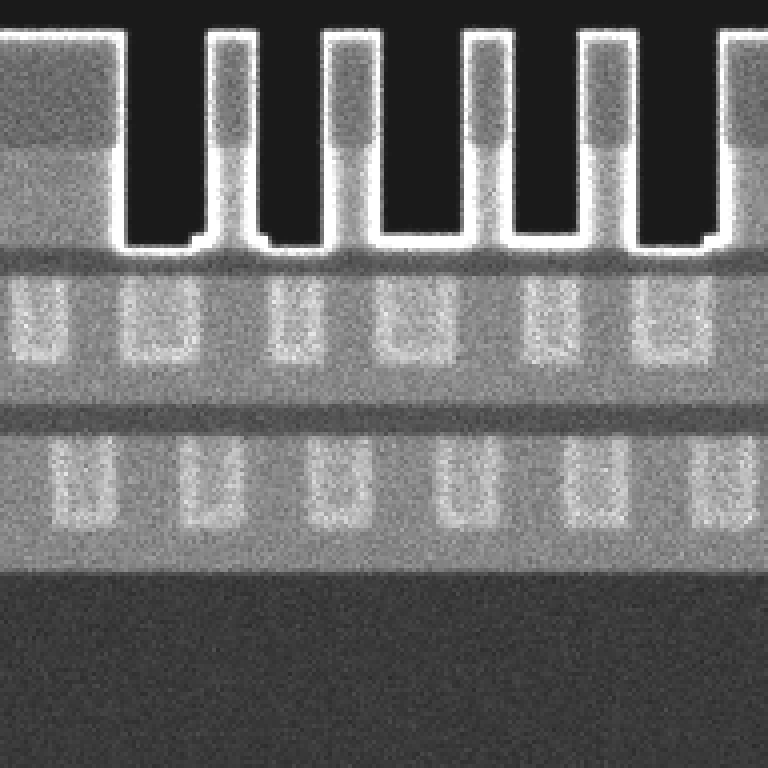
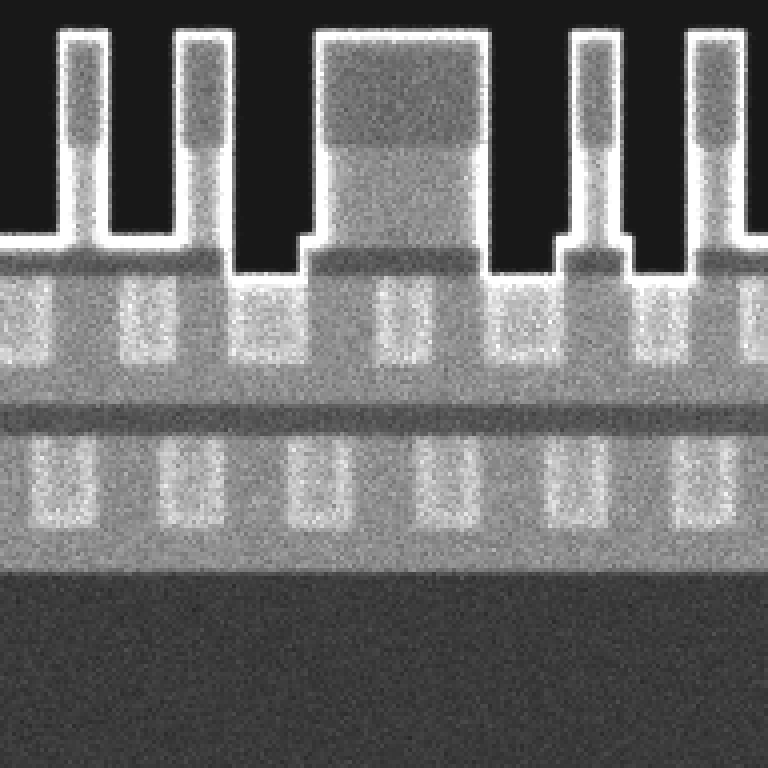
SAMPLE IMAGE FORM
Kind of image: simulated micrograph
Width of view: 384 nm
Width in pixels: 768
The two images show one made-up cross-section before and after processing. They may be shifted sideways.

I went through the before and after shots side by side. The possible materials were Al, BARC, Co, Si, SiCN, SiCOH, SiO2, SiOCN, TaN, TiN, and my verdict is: removed, SiCN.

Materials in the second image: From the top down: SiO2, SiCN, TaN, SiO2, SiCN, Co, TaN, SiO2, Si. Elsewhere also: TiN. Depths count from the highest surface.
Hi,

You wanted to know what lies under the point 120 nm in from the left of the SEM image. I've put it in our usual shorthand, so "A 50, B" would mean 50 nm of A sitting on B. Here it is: empty 122, TaN 44, SiO2 20, SiCN 16, SiO2 68, Si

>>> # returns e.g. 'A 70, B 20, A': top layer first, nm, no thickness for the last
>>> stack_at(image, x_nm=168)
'TiN 58, SiO2 50, SiCN 14, SiO2 64, SiCN 16, TaN 46, SiO2 22, Si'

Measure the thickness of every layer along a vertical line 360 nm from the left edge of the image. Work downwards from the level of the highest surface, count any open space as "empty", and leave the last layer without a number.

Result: TiN 58, SiO2 50, SiCN 14, SiO2 64, SiCN 16, TaN 46, SiO2 22, Si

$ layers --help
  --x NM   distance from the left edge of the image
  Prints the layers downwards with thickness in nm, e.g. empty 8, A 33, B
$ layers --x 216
TiN 58, SiO2 50, SiCN 14, SiO2 64, SiCN 16, Co 38, TaN 8, SiO2 22, Si